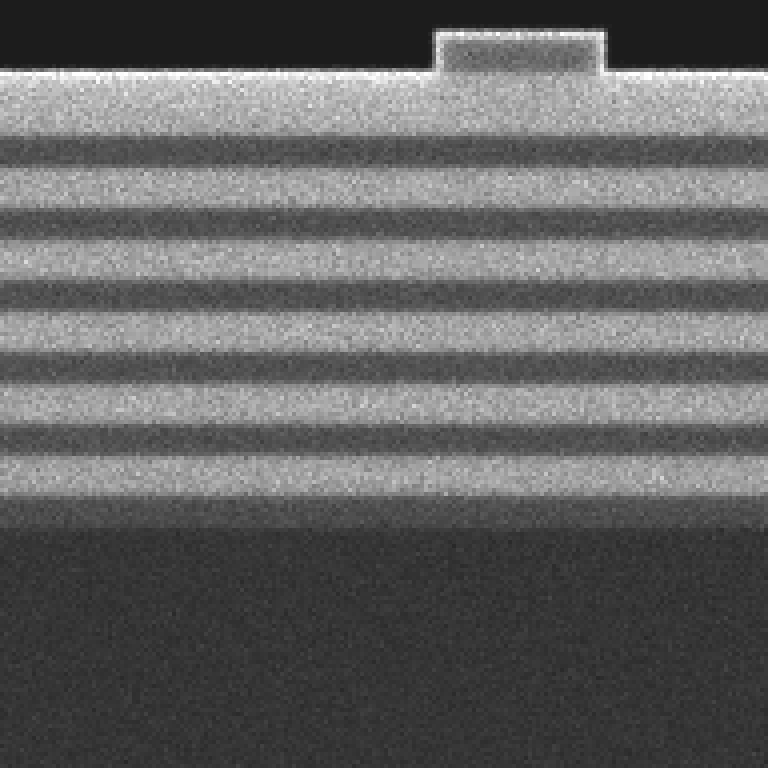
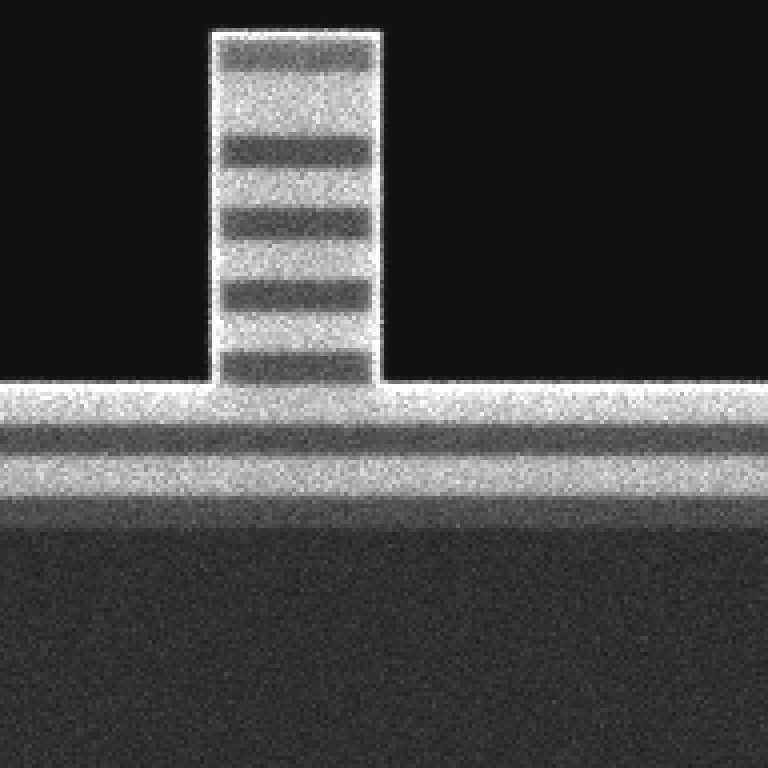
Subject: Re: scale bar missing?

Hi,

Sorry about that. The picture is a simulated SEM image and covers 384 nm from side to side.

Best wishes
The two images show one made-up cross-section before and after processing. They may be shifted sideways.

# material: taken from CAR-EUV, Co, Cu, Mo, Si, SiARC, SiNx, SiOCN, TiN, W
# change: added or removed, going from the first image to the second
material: SiNx and W
change: removed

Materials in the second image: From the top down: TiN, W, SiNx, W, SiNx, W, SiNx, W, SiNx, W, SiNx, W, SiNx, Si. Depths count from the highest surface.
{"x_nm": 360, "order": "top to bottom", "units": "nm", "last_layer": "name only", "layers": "empty 176, W 20, SiNx 16, W 20, SiNx 16, Si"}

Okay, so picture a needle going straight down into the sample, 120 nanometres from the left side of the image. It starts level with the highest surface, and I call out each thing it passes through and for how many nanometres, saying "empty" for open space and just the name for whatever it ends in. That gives TiN 20, W 32, SiNx 16, W 20, SiNx 16, W 20, SiNx 16, W 20, SiNx 16, W 20, SiNx 16, W 20, SiNx 16, Si